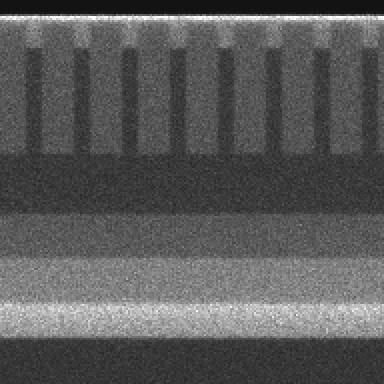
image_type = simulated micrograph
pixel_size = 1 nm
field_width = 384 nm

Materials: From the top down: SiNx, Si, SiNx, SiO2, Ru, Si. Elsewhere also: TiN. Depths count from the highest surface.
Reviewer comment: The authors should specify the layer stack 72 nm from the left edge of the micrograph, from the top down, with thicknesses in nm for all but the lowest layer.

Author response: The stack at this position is SiNx 138, Si 60, SiNx 44, SiO2 46, Ru 34, Si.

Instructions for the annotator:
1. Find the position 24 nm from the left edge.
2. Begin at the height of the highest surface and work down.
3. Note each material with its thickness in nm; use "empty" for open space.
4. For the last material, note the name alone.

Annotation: SiNx 138, Si 60, SiNx 44, SiO2 46, Ru 34, Si